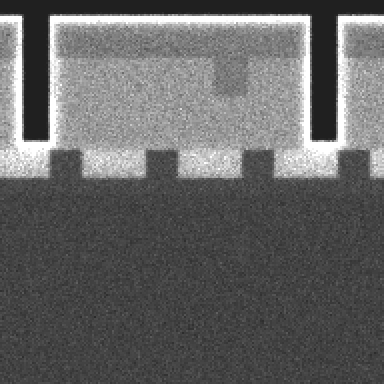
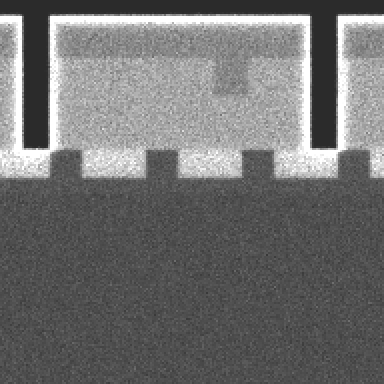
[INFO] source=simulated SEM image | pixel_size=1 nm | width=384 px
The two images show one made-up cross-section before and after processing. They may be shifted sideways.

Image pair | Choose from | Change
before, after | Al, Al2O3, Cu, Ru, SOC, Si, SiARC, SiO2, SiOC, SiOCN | Al2O3 (removed)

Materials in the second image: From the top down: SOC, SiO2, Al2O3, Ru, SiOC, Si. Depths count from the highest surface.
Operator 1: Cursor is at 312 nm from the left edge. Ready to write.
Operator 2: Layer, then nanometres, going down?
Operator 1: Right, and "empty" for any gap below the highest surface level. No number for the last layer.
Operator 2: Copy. empty 134, Ru 28, SiOC 16, Si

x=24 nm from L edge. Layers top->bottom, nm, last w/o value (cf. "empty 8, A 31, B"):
empty 134, Ru 28, SiOC 16, Si